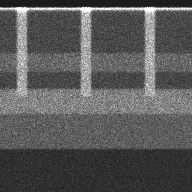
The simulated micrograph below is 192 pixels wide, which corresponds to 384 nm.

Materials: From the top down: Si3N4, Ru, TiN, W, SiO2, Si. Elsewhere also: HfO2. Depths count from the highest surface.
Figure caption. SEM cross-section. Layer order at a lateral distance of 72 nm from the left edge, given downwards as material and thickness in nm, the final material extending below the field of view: Si3N4 90, Ru 38, TiN 34, W 50, SiO2 70, Si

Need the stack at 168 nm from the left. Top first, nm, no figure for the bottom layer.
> HfO2 176, W 36, SiO2 70, Si